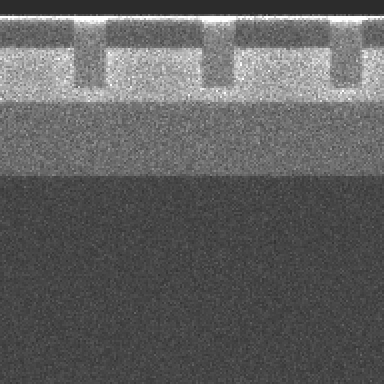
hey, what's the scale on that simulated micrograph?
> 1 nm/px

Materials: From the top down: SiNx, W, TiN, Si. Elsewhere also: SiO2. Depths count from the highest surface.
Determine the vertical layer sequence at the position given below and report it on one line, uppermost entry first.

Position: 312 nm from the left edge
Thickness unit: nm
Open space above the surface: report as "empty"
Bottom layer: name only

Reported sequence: SiNx 32, W 54, TiN 74, Si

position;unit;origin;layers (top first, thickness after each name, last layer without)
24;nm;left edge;SiNx 32, W 54, TiN 74, Si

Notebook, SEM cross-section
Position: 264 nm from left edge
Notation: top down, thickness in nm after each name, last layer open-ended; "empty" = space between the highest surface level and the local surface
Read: SiNx 32, W 54, TiN 74, Si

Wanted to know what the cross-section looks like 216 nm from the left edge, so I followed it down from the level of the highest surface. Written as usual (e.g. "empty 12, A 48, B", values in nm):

SiO2 72, W 14, TiN 74, Si